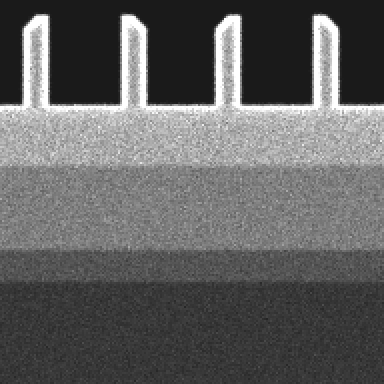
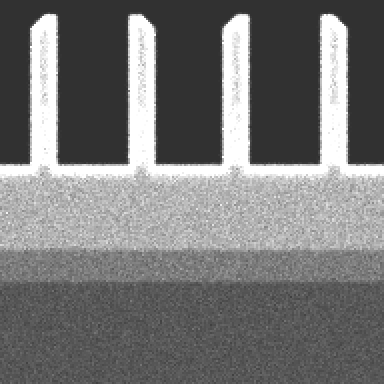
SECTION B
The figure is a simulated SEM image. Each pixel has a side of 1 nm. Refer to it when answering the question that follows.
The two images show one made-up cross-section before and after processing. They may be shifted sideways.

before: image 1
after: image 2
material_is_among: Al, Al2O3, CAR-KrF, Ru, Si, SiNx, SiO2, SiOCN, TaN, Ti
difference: Ru, removed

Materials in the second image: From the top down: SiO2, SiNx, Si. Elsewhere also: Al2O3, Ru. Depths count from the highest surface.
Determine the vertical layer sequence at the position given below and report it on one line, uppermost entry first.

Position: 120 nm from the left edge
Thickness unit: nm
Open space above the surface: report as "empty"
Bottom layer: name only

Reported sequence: empty 150, SiO2 84, SiNx 32, Si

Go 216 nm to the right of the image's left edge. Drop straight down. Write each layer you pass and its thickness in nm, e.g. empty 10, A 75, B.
empty 150, SiO2 84, SiNx 32, Si